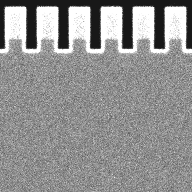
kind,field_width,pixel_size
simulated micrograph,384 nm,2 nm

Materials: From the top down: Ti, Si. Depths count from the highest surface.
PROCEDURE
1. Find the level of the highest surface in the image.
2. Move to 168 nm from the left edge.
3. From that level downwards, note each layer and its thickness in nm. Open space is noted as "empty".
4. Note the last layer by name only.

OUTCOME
Ti 62, Si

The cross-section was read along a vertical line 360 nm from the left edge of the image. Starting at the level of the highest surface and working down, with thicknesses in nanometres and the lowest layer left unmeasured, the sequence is Ti 62, Si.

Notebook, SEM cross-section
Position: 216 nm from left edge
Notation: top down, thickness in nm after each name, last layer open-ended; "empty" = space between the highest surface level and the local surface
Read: Ti 62, Si